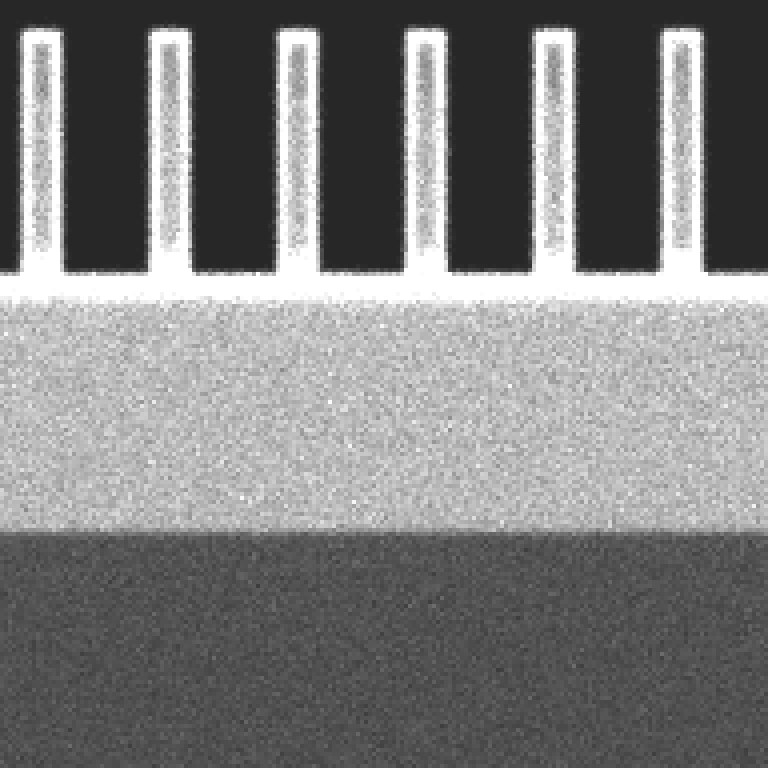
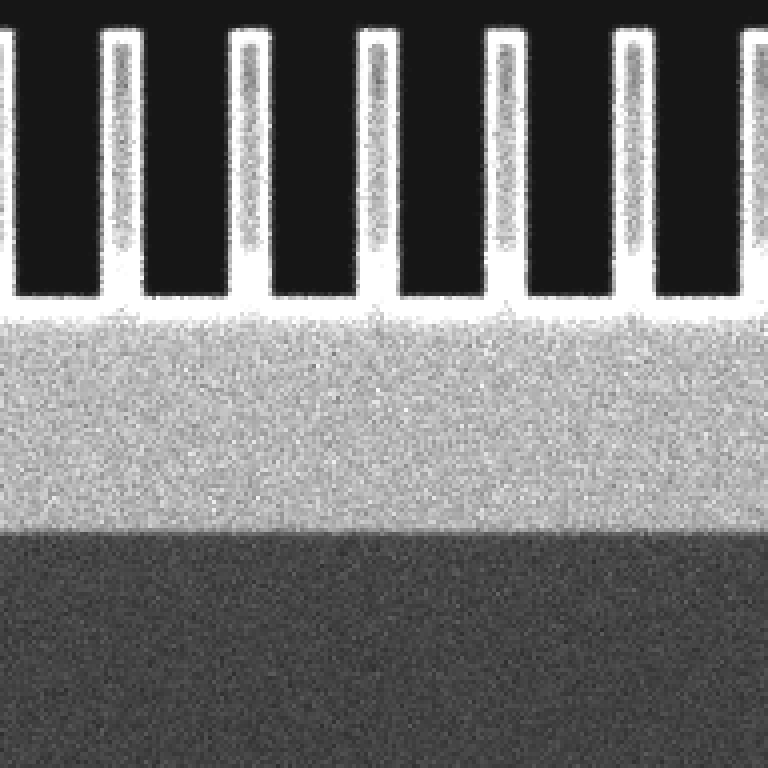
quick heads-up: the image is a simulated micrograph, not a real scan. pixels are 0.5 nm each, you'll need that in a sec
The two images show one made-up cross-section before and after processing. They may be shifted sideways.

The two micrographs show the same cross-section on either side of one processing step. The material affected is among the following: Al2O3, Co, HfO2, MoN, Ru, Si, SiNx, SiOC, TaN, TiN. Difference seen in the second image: Ru removed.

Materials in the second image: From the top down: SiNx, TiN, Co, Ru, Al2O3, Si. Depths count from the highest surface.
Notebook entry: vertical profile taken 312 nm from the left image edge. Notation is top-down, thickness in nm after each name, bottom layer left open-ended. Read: SiNx 32, TiN 78, Co 12, Ru 12, Al2O3 116, Si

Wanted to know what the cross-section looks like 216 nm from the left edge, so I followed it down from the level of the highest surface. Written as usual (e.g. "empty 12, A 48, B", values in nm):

empty 134, Al2O3 116, Si